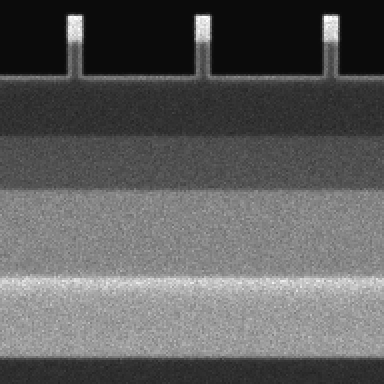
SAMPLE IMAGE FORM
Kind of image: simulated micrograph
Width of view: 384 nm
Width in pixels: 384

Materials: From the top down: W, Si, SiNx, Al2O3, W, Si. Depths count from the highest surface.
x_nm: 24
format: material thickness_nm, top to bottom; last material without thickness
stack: empty 60, Si 60, SiNx 54, Al2O3 88, W 80, Si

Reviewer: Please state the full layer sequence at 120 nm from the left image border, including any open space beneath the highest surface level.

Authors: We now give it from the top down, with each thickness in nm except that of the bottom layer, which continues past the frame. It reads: empty 60, Si 60, SiNx 54, Al2O3 88, W 80, Si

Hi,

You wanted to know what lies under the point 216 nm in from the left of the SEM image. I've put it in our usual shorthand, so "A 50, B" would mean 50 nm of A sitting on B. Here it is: empty 60, Si 60, SiNx 54, Al2O3 88, W 80, Si